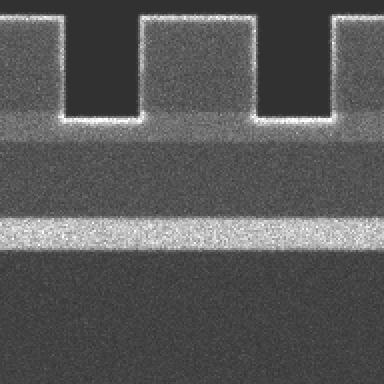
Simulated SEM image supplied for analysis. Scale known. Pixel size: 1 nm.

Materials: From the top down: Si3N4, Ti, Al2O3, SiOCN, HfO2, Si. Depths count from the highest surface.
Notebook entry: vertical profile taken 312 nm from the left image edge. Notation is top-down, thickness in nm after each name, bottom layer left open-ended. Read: empty 102, Al2O3 24, SiOCN 76, HfO2 32, Si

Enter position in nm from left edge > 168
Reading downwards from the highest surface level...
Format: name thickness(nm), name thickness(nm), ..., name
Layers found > Si3N4 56, Ti 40, Al2O3 30, SiOCN 76, HfO2 32, Si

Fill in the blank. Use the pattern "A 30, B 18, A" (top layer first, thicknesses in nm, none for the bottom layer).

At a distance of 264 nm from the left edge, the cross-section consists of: empty 102, Al2O3 24, SiOCN 76, HfO2 32, Si